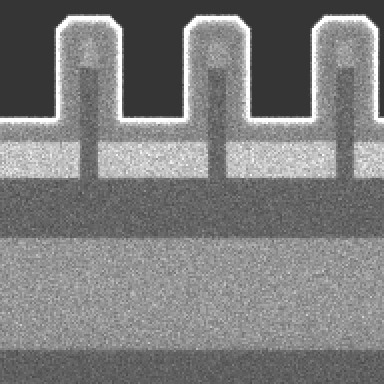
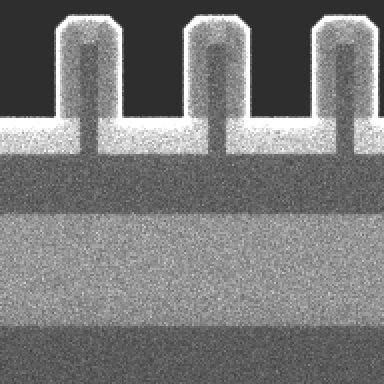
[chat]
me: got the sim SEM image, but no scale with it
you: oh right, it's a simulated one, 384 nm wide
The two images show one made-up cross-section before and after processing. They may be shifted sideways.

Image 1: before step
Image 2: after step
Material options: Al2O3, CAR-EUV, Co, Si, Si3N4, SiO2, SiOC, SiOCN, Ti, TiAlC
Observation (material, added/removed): SiOCN, removed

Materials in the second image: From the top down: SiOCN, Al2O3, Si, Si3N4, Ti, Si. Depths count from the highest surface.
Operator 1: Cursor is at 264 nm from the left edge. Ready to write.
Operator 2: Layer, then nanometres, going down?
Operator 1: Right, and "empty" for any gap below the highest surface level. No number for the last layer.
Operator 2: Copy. empty 102, Al2O3 36, Si 60, Si3N4 82, Ti 30, Si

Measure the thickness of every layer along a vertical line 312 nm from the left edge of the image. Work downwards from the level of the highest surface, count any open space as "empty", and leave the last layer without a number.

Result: empty 12, SiOCN 90, Al2O3 36, Si 60, Si3N4 82, Ti 30, Si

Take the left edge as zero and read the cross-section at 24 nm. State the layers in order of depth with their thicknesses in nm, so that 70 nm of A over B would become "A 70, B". empty 102, Al2O3 36, Si 60, Si3N4 82, Ti 30, Si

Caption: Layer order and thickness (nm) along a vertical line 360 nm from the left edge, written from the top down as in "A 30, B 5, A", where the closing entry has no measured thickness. SiOCN 102, Al2O3 36, Si 60, Si3N4 82, Ti 30, Si